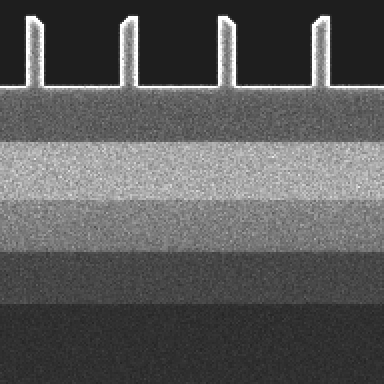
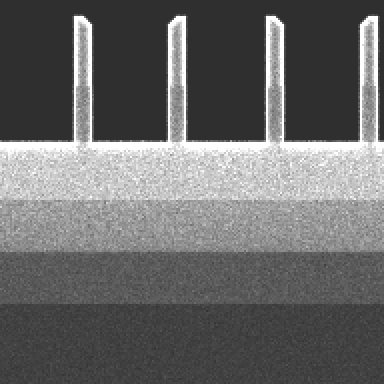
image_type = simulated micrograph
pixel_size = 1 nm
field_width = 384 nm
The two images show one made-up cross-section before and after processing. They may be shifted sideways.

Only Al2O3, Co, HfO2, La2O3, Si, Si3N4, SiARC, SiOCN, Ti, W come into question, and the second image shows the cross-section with Co removed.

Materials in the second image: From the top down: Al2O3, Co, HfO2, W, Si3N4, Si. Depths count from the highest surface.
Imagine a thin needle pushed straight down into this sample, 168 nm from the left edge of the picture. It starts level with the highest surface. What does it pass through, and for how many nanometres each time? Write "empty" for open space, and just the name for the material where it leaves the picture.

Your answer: empty 8, Al2O3 62, Co 56, HfO2 58, W 52, Si3N4 52, Si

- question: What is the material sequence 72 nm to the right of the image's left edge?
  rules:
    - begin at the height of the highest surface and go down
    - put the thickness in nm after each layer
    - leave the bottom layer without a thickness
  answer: empty 126, HfO2 58, W 52, Si3N4 52, Si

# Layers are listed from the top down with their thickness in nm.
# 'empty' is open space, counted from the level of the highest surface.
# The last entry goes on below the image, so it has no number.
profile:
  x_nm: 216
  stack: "empty 126, HfO2 58, W 52, Si3N4 52, Si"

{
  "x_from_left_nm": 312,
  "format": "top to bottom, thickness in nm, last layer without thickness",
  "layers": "empty 126, HfO2 58, W 52, Si3N4 52, Si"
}